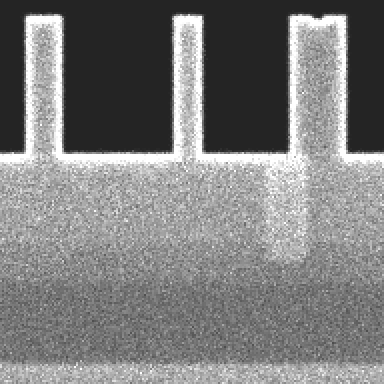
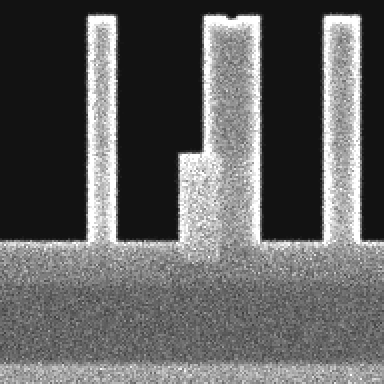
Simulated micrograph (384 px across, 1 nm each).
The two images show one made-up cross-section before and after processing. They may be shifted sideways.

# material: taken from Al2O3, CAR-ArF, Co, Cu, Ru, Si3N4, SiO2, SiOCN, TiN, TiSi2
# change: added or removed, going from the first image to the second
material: Al2O3
change: removed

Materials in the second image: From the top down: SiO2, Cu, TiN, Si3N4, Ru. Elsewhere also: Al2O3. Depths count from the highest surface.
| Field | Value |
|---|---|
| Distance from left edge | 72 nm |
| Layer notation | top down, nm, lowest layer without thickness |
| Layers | empty 226, TiN 42, Si3N4 80, Ru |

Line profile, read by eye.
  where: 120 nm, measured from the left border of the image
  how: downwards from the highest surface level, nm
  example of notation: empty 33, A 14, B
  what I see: empty 226, TiN 42, Si3N4 80, Ru